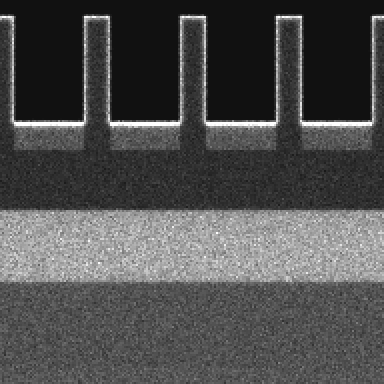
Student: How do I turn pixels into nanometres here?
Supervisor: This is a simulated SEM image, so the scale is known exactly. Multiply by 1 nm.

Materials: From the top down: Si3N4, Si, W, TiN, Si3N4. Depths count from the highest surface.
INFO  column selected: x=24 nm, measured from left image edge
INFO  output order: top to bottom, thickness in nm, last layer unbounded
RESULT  empty 106, Si3N4 28, Si 60, W 72, TiN 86, Si3N4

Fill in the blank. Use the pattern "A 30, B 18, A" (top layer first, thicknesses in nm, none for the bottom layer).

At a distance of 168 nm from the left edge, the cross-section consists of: empty 106, Si3N4 28, Si 60, W 72, TiN 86, Si3N4